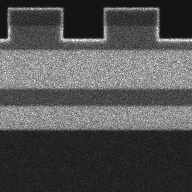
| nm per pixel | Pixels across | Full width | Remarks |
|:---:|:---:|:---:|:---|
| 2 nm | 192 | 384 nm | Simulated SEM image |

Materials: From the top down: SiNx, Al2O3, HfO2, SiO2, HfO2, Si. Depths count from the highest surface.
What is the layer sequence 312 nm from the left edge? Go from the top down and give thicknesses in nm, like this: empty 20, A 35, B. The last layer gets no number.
SiNx 36, Al2O3 48, HfO2 78, SiO2 34, HfO2 48, Si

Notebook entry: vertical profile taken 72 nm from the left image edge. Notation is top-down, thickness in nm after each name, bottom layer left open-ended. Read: SiNx 36, Al2O3 48, HfO2 78, SiO2 34, HfO2 48, Si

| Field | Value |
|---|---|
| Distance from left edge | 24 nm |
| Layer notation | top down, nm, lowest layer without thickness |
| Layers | SiNx 36, Al2O3 48, HfO2 78, SiO2 34, HfO2 48, Si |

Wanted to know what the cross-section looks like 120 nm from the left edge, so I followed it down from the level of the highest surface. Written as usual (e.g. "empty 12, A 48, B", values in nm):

SiNx 36, Al2O3 48, HfO2 78, SiO2 34, HfO2 48, Si